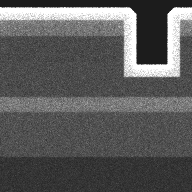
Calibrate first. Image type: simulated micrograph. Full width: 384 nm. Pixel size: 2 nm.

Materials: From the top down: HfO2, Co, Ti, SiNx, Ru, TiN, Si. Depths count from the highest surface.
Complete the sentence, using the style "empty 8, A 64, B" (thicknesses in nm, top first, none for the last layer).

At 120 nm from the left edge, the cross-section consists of HfO2 24, Co 32, Ti 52, SiNx 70, Ru 30, TiN 90, Si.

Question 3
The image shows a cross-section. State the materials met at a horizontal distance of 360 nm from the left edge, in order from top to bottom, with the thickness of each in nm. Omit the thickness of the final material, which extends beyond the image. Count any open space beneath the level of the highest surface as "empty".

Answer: HfO2 24, Co 32, Ti 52, SiNx 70, Ru 30, TiN 90, Si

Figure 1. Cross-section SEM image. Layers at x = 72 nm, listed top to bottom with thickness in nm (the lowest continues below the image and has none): HfO2 24, Co 32, Ti 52, SiNx 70, Ru 30, TiN 90, Si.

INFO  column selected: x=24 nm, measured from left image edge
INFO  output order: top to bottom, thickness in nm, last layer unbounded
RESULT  HfO2 24, Co 32, Ti 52, SiNx 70, Ru 30, TiN 90, Si